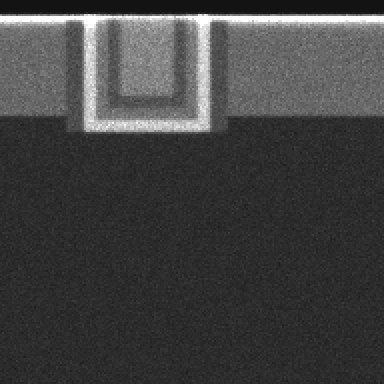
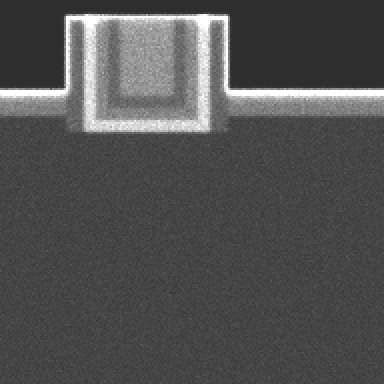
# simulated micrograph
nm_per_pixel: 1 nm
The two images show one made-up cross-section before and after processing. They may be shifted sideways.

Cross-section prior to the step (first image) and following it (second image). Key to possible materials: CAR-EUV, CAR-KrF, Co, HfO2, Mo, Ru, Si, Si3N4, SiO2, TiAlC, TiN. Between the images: SiO2 was removed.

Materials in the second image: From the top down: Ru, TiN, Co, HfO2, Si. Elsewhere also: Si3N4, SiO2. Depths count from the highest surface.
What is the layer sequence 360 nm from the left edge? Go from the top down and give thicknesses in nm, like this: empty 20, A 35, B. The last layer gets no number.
empty 74, SiO2 26, Si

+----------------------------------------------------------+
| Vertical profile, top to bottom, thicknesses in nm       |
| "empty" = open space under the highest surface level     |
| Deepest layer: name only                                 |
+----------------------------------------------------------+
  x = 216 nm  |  Si3N4 116, Si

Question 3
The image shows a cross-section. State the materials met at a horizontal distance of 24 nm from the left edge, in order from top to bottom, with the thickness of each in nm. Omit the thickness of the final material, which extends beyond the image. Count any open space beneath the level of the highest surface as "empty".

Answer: empty 74, SiO2 26, Si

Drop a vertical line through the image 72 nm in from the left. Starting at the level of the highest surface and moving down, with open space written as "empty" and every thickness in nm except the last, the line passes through Si3N4 116, Si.